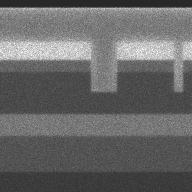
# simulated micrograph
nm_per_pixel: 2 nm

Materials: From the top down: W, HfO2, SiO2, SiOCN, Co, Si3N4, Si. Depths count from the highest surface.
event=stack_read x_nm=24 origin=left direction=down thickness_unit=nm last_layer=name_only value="W 68, HfO2 36, SiO2 24, SiOCN 84, Co 44, Si3N4 72, Si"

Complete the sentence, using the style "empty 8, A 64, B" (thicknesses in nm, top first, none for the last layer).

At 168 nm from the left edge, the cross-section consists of W 68, HfO2 36, SiO2 24, SiOCN 84, Co 44, Si3N4 72, Si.